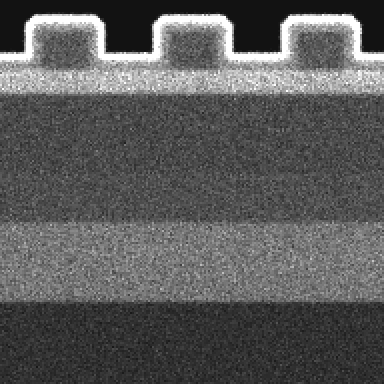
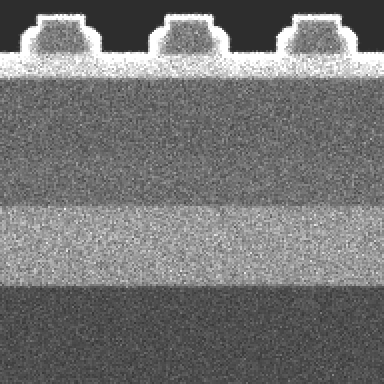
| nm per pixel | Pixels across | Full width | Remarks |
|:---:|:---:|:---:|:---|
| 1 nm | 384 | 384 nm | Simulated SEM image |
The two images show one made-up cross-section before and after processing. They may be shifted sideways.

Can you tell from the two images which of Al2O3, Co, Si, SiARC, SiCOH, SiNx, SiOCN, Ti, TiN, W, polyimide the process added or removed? Yes, it removed Al2O3.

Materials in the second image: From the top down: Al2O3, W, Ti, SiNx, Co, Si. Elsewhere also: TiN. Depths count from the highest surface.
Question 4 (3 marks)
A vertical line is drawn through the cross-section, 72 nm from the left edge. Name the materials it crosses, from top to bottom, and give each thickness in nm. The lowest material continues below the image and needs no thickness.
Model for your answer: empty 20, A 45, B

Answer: TiN 38, W 24, Ti 78, SiNx 50, Co 80, Si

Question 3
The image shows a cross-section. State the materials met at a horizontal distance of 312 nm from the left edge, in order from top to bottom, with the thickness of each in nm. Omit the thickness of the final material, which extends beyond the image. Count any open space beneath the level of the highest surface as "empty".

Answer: TiN 38, W 24, Ti 78, SiNx 50, Co 80, Si